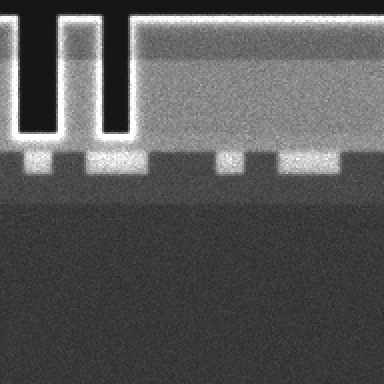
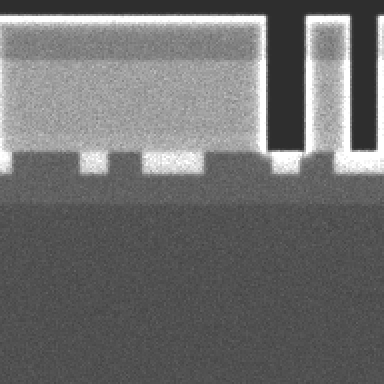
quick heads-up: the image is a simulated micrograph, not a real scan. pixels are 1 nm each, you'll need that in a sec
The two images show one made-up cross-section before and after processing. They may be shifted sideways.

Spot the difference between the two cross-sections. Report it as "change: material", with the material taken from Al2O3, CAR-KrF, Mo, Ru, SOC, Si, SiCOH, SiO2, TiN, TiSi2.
removed: Al2O3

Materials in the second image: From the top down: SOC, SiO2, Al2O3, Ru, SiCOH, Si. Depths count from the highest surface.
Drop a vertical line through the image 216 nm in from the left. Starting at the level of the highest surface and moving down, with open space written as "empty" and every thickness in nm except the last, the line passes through SOC 44, SiO2 74, Al2O3 18, SiCOH 52, Si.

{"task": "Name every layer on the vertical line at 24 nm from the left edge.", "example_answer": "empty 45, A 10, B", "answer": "SOC 44, SiO2 74, Al2O3 18, SiCOH 52, Si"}